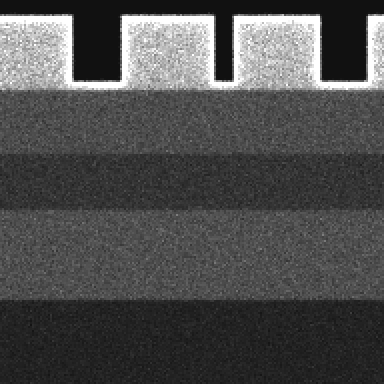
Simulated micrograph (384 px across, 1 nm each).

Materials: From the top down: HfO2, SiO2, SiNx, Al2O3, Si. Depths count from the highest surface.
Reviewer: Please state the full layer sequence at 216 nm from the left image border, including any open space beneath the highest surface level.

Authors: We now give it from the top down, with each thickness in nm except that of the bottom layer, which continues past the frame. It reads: empty 66, HfO2 8, SiO2 64, SiNx 56, Al2O3 90, Si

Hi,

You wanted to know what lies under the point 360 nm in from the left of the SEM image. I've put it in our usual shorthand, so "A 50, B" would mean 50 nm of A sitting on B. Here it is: empty 66, HfO2 8, SiO2 64, SiNx 56, Al2O3 90, Si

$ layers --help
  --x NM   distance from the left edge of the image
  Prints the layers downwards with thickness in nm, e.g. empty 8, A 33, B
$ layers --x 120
empty 66, HfO2 8, SiO2 64, SiNx 56, Al2O3 90, Si